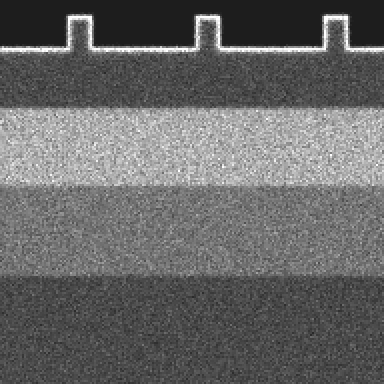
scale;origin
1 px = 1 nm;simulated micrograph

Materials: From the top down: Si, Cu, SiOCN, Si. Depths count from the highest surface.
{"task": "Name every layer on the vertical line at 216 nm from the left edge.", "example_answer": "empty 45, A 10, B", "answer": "Si 92, Cu 78, SiOCN 90, Si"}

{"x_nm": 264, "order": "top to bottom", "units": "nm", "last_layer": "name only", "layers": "empty 32, Si 60, Cu 78, SiOCN 90, Si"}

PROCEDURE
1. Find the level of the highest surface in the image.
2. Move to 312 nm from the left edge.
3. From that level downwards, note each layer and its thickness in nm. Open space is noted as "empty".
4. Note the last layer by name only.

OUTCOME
empty 32, Si 60, Cu 78, SiOCN 90, Si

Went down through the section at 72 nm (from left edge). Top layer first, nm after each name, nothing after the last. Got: Si 92, Cu 78, SiOCN 90, Si